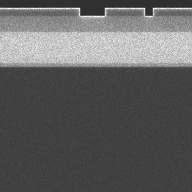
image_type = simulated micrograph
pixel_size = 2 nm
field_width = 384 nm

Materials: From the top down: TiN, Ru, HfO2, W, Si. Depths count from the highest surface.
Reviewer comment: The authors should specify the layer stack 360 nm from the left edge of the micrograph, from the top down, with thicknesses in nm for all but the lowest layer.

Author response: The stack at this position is TiN 16, Ru 32, HfO2 62, W 8, Si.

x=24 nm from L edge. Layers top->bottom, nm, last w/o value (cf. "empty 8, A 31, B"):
TiN 16, Ru 32, HfO2 62, W 8, Si